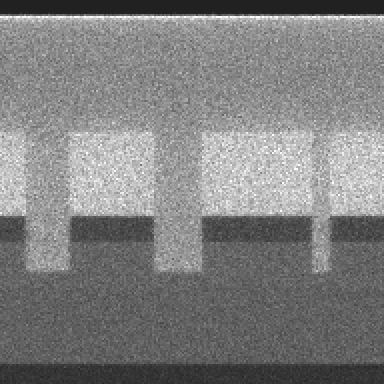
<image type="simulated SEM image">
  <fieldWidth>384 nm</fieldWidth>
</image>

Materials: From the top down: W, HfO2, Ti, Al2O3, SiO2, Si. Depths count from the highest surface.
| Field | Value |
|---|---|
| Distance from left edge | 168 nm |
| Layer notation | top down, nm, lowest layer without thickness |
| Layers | W 256, Al2O3 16, SiO2 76, Si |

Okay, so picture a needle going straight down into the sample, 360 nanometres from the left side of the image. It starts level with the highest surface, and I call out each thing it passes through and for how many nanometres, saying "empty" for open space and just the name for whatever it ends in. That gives W 116, HfO2 84, Ti 26, Al2O3 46, SiO2 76, Si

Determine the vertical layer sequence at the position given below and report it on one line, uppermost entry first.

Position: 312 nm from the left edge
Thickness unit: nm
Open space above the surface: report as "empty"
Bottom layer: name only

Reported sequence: W 256, Al2O3 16, SiO2 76, Si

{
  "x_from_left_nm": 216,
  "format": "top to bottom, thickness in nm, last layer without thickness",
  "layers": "W 116, HfO2 84, Ti 26, Al2O3 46, SiO2 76, Si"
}